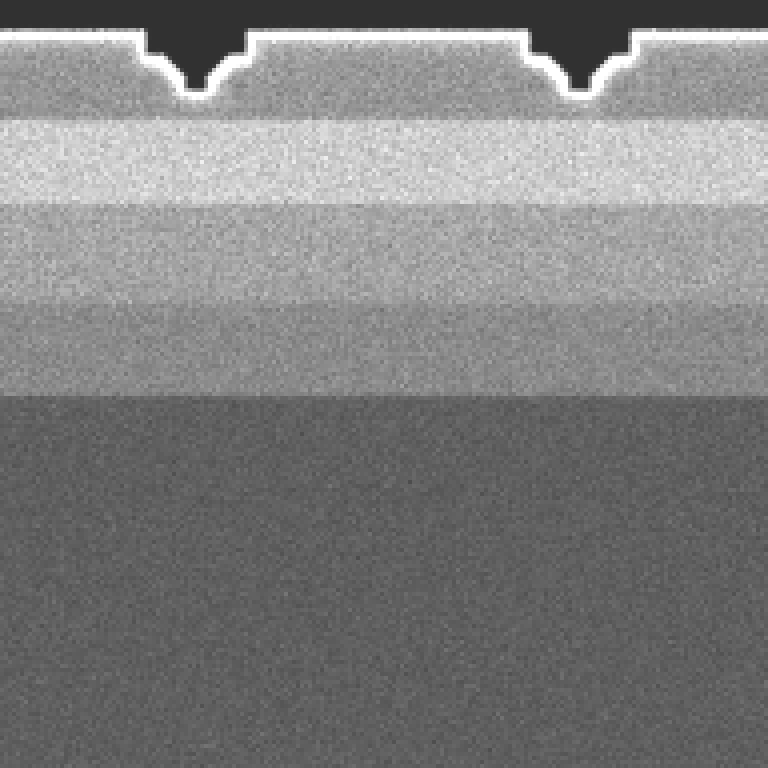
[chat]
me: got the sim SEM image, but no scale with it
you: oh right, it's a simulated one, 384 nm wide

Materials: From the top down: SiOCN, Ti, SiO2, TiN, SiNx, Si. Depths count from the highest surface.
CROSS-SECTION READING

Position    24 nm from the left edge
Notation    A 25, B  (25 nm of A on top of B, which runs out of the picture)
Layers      Ti 44, SiO2 42, TiN 50, SiNx 46, Si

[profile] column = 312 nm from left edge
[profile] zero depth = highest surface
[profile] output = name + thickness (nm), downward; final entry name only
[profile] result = empty 12, SiOCN 18, Ti 14, SiO2 42, TiN 50, SiNx 46, Si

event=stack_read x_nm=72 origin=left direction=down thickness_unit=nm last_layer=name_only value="empty 12, SiOCN 18, Ti 14, SiO2 42, TiN 50, SiNx 46, Si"